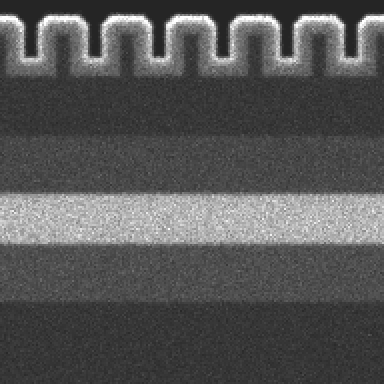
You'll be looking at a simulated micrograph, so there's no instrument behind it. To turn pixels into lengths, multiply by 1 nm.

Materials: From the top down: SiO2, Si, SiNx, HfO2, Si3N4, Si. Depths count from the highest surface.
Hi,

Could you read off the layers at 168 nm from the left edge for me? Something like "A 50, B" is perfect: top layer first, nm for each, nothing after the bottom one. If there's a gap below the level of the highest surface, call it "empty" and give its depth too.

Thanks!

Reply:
empty 6, SiO2 54, Si 60, SiNx 58, HfO2 50, Si3N4 58, Si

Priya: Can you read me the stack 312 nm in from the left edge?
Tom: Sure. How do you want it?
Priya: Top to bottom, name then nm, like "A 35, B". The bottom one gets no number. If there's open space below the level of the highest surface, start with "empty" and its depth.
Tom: SiO2 18, Si 102, SiNx 58, HfO2 50, Si3N4 58, Si